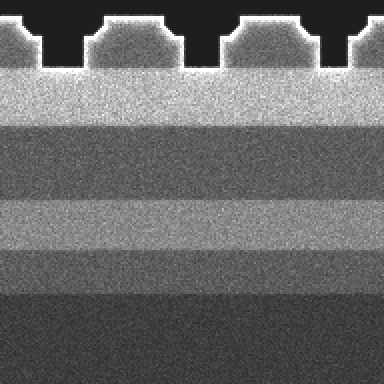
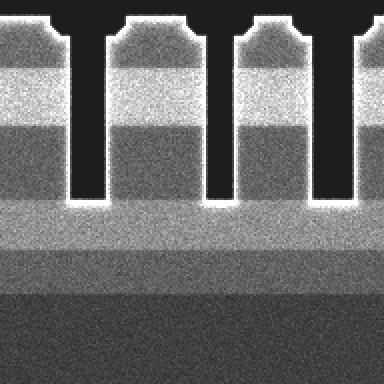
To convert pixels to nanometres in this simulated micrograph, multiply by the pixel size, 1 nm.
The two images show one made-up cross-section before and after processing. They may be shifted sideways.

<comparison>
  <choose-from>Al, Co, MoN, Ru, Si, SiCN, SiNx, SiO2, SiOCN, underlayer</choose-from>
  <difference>Ru and SiNx removed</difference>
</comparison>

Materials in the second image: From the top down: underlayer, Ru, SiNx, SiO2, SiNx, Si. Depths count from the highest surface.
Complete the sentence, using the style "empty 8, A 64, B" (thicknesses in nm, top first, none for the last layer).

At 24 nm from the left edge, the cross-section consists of underlayer 52, Ru 58, SiNx 74, SiO2 50, SiNx 44, Si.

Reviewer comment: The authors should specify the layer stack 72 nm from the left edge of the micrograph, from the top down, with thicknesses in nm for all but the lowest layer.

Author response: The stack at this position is empty 184, SiO2 50, SiNx 44, Si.